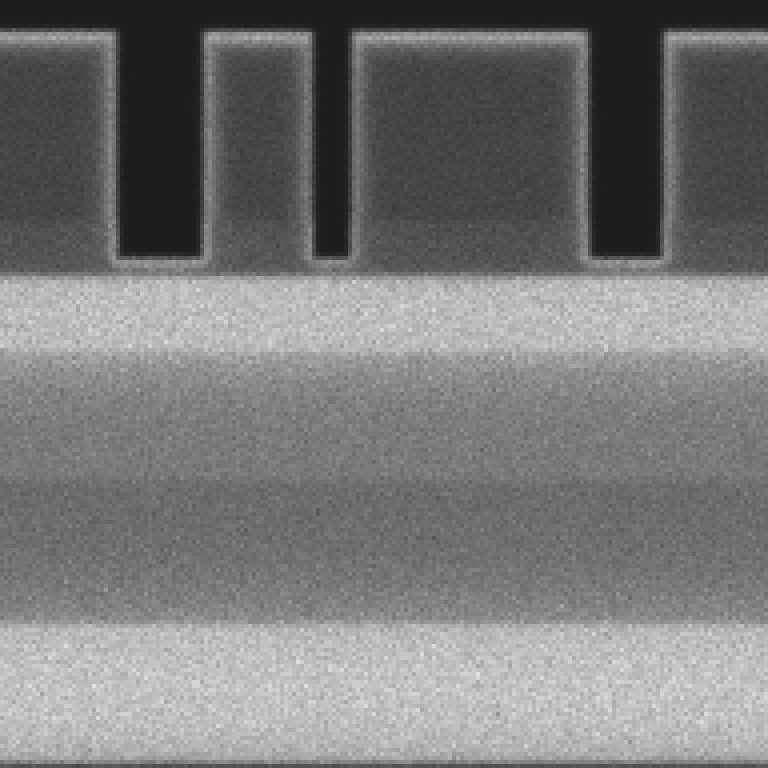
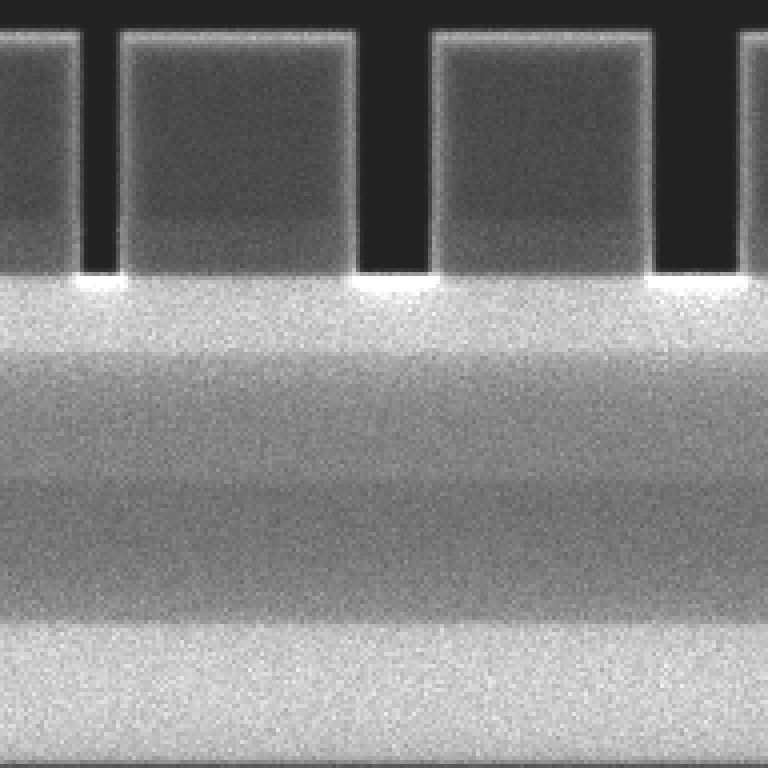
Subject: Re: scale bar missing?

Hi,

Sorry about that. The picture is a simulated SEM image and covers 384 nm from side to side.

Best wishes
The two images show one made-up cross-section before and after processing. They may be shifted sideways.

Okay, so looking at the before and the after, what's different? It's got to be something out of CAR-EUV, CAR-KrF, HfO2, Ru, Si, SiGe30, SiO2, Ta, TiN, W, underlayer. TiN, removed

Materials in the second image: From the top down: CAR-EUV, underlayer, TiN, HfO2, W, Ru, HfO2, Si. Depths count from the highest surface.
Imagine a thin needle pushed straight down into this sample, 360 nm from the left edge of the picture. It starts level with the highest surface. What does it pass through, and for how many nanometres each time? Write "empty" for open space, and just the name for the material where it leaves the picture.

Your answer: empty 122, HfO2 38, W 64, Ru 72, HfO2 70, Si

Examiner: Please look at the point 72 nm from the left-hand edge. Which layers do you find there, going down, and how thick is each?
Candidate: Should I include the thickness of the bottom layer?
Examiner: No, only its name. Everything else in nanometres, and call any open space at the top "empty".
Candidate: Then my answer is CAR-EUV 50, underlayer 44, TiN 28, HfO2 38, W 64, Ru 72, HfO2 70, Si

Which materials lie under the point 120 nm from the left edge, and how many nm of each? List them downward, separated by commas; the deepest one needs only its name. CAR-EUV 50, underlayer 44, TiN 28, HfO2 38, W 64, Ru 72, HfO2 70, Si